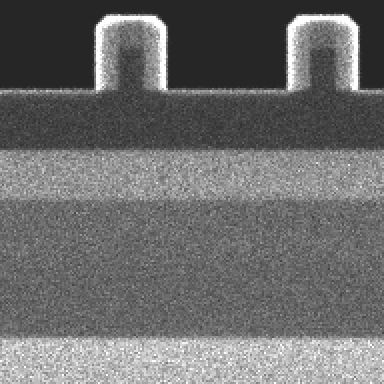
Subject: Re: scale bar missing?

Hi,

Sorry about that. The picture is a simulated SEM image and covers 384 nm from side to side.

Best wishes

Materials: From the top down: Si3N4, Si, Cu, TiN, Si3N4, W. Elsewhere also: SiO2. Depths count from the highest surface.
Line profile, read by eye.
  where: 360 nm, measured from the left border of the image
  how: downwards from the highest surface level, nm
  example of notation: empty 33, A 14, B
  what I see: empty 74, Si 60, Cu 50, TiN 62, Si3N4 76, W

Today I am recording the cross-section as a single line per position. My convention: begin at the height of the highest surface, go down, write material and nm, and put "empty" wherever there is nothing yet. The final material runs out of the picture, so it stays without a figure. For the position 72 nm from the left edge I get empty 74, Si 60, Cu 50, TiN 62, Si3N4 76, W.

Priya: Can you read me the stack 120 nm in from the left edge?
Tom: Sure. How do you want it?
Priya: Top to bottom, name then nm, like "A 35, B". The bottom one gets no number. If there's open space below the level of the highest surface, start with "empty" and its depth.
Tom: Si3N4 32, Si 102, Cu 50, TiN 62, Si3N4 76, W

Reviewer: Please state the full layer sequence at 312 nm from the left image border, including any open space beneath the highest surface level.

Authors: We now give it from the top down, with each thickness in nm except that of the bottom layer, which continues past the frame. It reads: Si3N4 32, Si 102, Cu 50, TiN 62, Si3N4 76, W